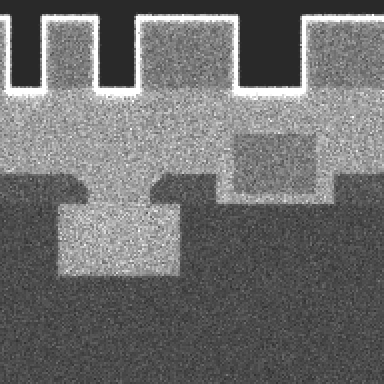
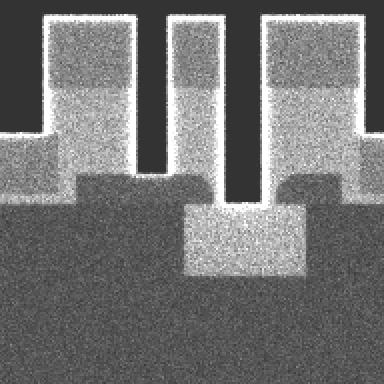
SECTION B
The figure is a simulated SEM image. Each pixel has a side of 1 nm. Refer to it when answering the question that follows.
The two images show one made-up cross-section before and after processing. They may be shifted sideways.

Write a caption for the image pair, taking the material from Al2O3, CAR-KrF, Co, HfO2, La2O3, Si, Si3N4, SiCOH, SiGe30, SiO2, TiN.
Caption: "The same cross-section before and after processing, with SiO2 removed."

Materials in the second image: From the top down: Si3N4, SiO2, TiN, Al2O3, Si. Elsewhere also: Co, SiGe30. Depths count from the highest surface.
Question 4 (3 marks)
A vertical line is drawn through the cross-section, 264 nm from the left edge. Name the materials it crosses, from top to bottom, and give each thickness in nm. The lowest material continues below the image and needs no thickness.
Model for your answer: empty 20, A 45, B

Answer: Si3N4 72, SiO2 116, Co 72, Si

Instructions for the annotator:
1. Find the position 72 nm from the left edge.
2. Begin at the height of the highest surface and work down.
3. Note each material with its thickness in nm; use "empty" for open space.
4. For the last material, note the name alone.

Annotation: Si3N4 72, SiO2 52, Al2O3 64, Si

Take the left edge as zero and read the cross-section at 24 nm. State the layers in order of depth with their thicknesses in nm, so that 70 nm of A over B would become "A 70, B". empty 118, TiN 60, Al2O3 10, Si